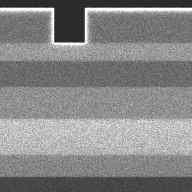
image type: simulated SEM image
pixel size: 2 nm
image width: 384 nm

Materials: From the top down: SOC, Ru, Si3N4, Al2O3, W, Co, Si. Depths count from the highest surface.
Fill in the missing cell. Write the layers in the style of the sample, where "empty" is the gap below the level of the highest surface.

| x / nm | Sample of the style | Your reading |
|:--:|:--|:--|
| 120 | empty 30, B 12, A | empty 70, Ru 36, Si3N4 52, Al2O3 64, W 72, Co 44, Si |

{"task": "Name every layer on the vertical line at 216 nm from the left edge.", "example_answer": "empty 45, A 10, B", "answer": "SOC 70, Ru 36, Si3N4 52, Al2O3 64, W 72, Co 44, Si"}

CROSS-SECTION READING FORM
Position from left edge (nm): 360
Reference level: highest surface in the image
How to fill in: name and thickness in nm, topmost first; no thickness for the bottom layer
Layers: SOC 70, Ru 36, Si3N4 52, Al2O3 64, W 72, Co 44, Si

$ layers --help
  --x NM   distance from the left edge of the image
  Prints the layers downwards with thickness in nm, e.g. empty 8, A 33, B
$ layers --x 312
SOC 70, Ru 36, Si3N4 52, Al2O3 64, W 72, Co 44, Si